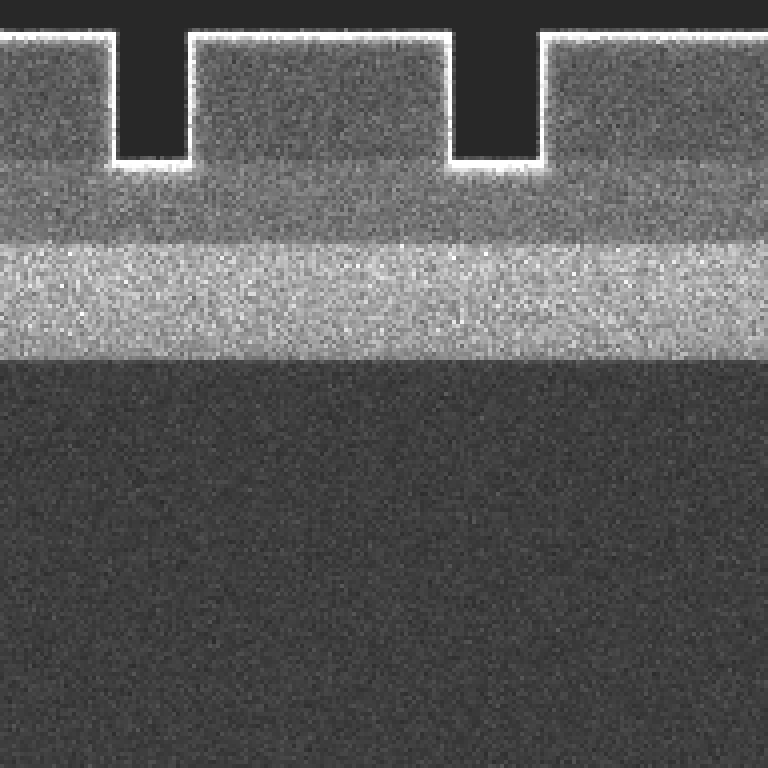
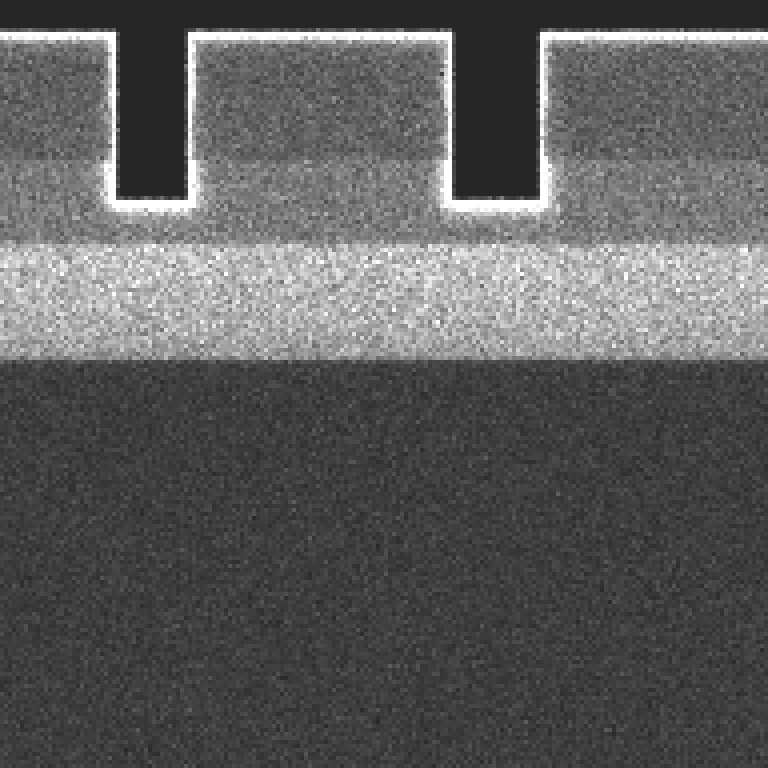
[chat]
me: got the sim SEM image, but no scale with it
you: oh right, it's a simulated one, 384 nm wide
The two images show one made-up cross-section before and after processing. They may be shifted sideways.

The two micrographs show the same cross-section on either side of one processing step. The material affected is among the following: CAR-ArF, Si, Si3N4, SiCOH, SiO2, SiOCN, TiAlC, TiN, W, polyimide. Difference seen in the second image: SiO2 removed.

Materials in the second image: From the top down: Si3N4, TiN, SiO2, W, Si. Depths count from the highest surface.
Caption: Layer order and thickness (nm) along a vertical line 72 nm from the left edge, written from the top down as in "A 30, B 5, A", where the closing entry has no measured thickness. empty 84, SiO2 22, W 58, Si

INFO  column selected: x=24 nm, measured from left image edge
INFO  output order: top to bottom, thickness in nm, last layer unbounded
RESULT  Si3N4 38, TiN 26, SiO2 42, W 58, Si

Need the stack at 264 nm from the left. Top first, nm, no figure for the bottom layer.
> empty 84, SiO2 22, W 58, Si